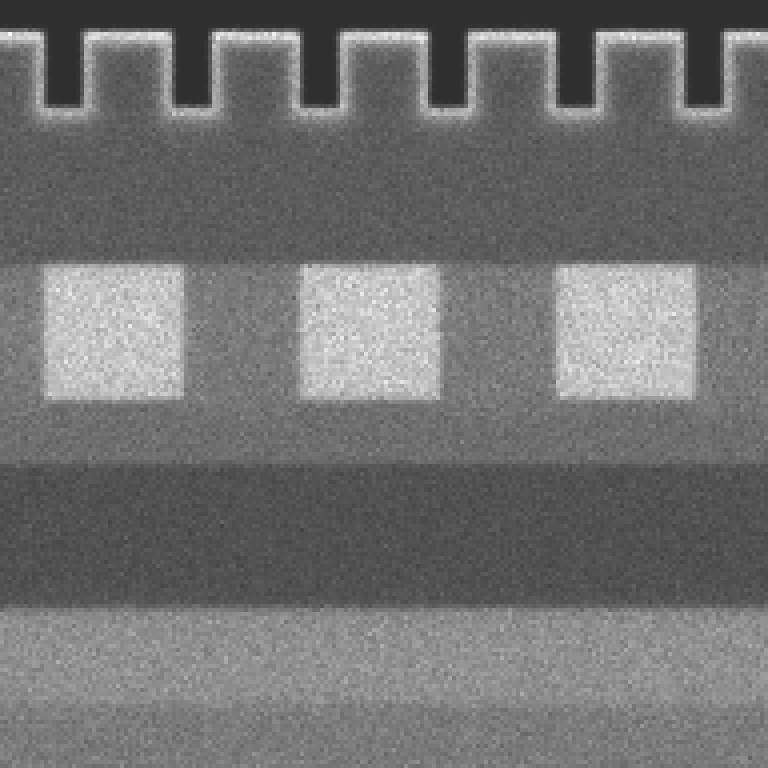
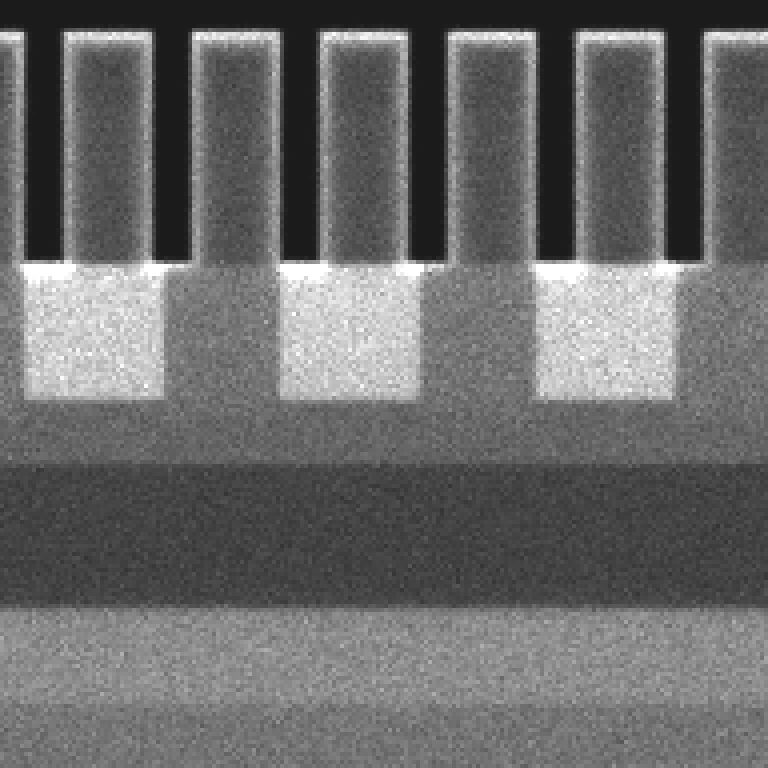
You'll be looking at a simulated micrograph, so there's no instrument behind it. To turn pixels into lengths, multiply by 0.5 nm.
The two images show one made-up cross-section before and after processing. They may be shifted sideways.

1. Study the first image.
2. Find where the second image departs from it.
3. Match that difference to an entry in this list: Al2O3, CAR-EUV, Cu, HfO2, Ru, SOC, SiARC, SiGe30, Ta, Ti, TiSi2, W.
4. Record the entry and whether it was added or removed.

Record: SOC / removed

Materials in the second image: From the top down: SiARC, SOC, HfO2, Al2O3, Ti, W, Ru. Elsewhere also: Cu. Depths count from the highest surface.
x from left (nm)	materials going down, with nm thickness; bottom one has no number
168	SiARC 38, SOC 78, HfO2 68, Al2O3 32, Ti 72, W 48, Ru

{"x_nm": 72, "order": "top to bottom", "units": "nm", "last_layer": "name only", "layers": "SiARC 38, SOC 78, HfO2 68, Al2O3 32, Ti 72, W 48, Ru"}